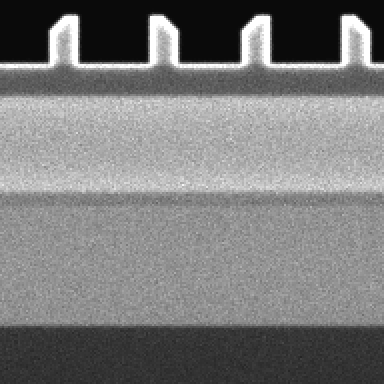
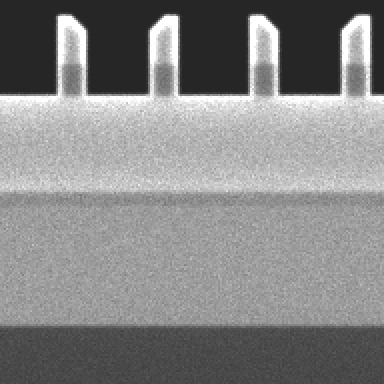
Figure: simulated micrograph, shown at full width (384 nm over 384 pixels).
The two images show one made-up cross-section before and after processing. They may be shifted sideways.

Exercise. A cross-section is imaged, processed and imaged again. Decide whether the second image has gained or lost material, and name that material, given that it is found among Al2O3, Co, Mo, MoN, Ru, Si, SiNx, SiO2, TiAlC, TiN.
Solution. removed: SiNx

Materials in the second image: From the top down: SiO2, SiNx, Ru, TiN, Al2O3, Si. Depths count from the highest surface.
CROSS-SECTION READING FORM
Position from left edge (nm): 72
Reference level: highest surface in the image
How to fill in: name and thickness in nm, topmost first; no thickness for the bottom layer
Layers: empty 2, SiO2 46, SiNx 32, Ru 96, TiN 14, Al2O3 120, Si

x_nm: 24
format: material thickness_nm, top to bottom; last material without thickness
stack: empty 80, Ru 96, TiN 14, Al2O3 120, Si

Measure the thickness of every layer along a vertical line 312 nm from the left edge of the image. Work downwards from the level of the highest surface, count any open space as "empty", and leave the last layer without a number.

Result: empty 80, Ru 96, TiN 14, Al2O3 120, Si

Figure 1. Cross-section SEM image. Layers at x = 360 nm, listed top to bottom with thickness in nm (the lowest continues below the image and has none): SiO2 48, SiNx 32, Ru 96, TiN 14, Al2O3 120, Si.